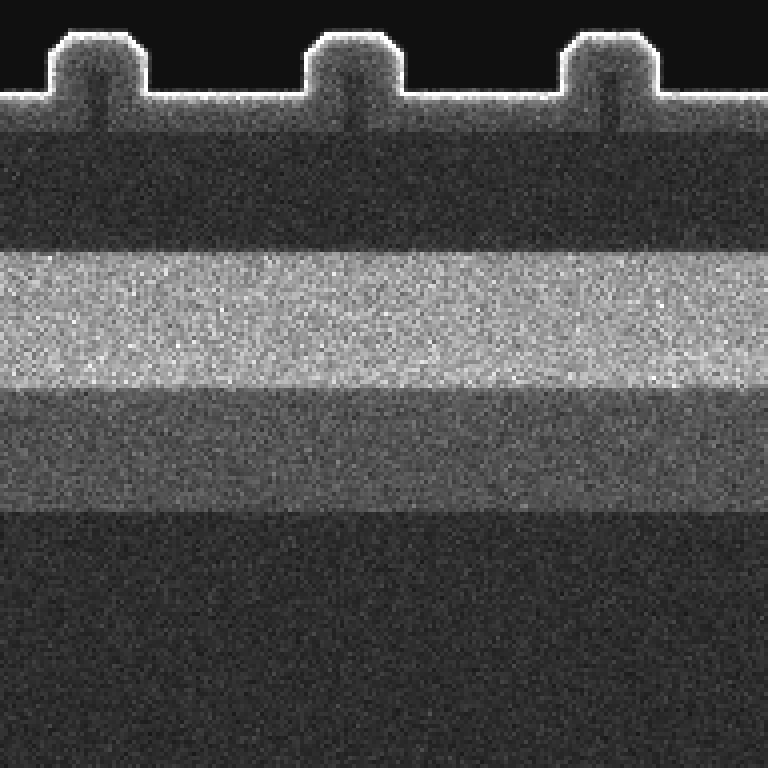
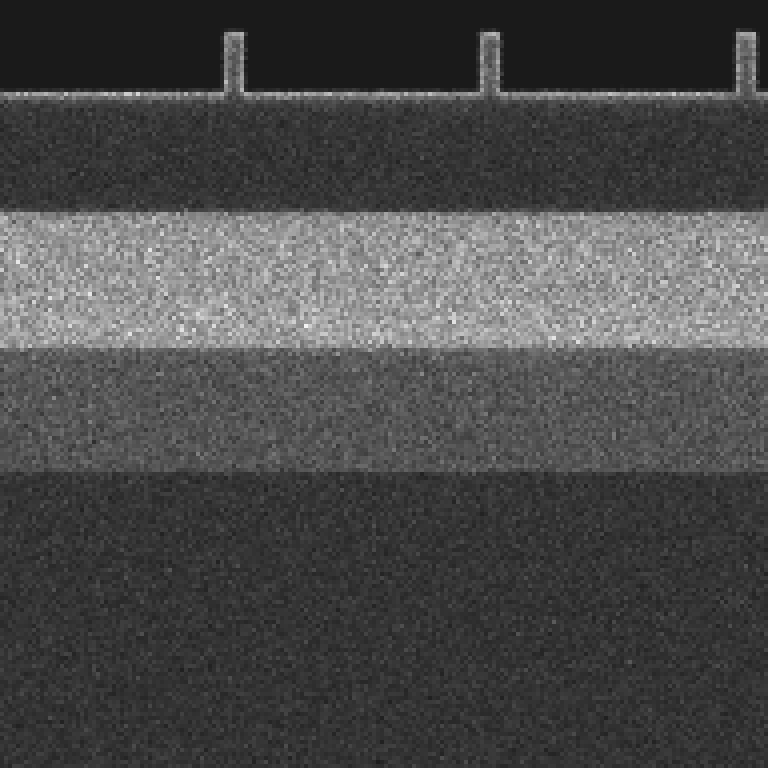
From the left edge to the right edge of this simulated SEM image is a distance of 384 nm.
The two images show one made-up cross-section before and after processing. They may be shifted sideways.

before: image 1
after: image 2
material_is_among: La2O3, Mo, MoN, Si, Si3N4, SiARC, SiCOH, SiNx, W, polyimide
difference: SiNx, removed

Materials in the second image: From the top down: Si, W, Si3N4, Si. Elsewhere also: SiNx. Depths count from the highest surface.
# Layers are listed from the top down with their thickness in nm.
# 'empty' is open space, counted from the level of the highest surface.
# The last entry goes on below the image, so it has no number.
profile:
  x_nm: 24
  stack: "empty 30, Si 60, W 68, Si3N4 62, Si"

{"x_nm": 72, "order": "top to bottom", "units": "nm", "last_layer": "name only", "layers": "empty 30, Si 60, W 68, Si3N4 62, Si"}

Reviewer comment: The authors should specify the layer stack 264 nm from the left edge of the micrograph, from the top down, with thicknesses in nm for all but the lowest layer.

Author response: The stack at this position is empty 30, Si 60, W 68, Si3N4 62, Si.